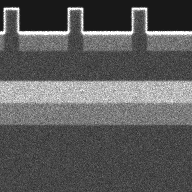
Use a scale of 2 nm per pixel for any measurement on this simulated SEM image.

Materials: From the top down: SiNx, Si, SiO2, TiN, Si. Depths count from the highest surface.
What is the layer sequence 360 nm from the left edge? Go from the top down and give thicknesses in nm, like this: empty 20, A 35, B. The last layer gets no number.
empty 48, SiNx 38, Si 60, SiO2 44, TiN 44, Si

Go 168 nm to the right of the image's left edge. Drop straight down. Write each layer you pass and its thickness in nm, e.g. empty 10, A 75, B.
empty 48, SiNx 38, Si 60, SiO2 44, TiN 44, Si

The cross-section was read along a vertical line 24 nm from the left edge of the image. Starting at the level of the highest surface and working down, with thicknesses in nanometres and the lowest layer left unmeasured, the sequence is Si 146, SiO2 44, TiN 44, Si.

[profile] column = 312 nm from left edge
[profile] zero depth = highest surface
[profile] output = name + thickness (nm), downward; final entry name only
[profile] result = empty 48, SiNx 38, Si 60, SiO2 44, TiN 44, Si